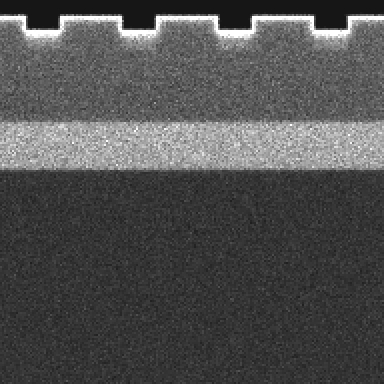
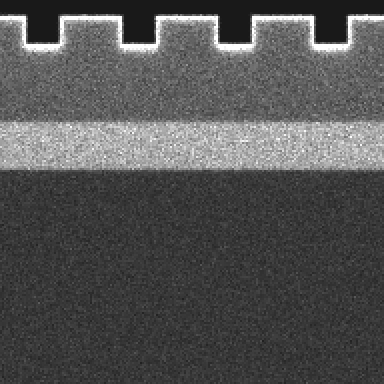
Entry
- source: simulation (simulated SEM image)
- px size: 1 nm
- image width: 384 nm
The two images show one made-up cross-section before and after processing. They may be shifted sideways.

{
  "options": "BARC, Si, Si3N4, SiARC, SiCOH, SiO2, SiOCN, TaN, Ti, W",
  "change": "removed",
  "material": "SiO2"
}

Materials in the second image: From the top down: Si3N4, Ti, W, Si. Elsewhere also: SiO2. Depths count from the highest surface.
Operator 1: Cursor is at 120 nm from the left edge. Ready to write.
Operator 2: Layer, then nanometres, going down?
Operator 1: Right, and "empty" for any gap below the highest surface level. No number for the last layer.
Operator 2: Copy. Si3N4 60, Ti 46, W 48, Si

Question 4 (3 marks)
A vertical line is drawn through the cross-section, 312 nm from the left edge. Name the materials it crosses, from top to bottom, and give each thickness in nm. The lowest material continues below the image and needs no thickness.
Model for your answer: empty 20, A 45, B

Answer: Si3N4 60, Ti 46, W 48, Si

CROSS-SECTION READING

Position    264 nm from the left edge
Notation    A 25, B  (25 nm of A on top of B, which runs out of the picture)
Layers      Si3N4 60, Ti 46, W 48, Si